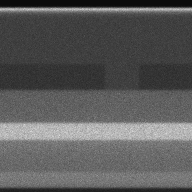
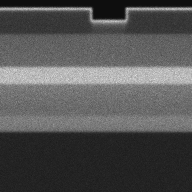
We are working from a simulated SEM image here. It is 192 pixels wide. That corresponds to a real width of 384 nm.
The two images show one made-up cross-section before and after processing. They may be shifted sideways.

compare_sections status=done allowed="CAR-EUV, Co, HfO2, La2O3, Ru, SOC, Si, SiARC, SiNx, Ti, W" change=removed material="SOC"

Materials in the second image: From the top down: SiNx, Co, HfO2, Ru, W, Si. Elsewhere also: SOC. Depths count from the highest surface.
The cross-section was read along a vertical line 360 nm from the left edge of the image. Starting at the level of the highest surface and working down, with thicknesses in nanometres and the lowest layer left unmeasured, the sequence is SiNx 52, Co 66, HfO2 34, Ru 64, W 32, Si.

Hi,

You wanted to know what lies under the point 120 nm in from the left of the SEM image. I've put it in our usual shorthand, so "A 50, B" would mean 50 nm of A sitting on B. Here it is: SiNx 52, Co 66, HfO2 34, Ru 64, W 32, Si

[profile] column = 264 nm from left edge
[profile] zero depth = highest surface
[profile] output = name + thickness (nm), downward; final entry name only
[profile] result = SiNx 52, Co 66, HfO2 34, Ru 64, W 32, Si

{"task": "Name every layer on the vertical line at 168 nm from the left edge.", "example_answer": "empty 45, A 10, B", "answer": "SiNx 52, Co 66, HfO2 34, Ru 64, W 32, Si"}